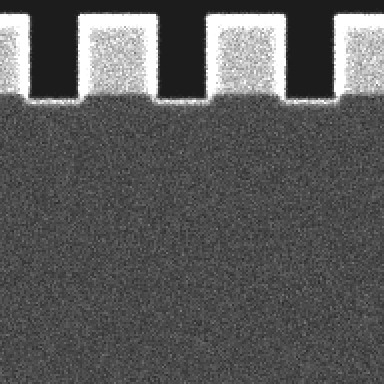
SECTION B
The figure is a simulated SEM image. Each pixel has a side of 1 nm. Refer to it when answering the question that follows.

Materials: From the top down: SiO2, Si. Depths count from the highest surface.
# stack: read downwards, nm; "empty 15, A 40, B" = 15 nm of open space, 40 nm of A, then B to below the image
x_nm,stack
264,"SiO2 78, Si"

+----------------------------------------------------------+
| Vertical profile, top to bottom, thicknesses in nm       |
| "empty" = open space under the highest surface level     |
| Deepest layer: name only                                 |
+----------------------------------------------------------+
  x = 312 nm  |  empty 84, Si